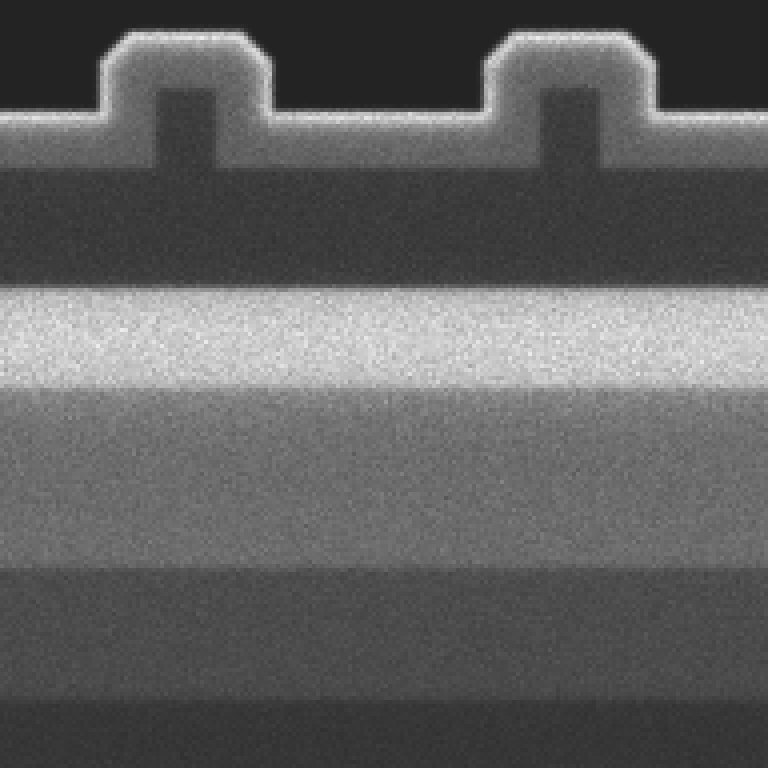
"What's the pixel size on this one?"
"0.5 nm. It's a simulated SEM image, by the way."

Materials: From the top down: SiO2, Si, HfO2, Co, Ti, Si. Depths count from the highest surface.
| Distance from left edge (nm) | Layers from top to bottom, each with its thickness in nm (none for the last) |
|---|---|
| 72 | SiO2 68, Si 60, HfO2 50, Co 90, Ti 66, Si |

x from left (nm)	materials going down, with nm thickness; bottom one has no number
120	SiO2 68, Si 60, HfO2 50, Co 90, Ti 66, Si